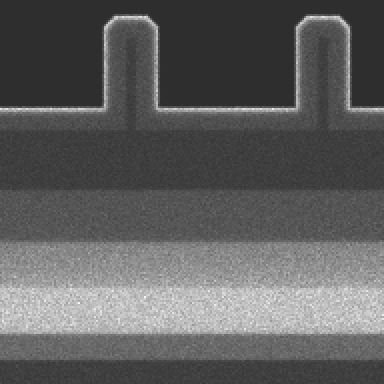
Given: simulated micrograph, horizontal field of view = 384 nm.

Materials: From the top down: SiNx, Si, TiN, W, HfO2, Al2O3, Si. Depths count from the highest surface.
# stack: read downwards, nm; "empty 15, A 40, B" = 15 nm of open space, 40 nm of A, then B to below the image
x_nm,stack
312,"SiNx 114, Si 60, TiN 52, W 46, HfO2 46, Al2O3 26, Si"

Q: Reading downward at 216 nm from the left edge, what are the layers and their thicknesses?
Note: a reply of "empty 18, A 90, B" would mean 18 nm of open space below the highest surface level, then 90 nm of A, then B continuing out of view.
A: empty 92, SiNx 22, Si 60, TiN 52, W 46, HfO2 46, Al2O3 26, Si